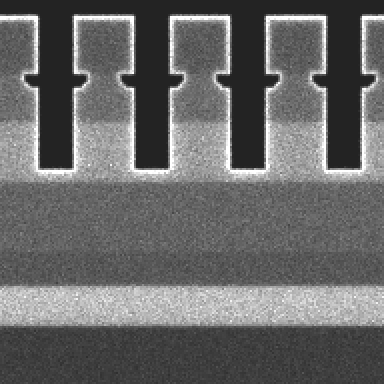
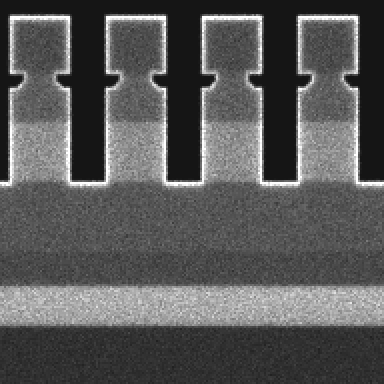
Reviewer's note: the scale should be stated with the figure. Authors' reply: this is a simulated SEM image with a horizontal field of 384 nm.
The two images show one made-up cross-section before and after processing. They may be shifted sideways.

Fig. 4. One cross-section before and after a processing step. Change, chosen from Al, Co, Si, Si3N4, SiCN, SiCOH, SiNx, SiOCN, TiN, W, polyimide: Co removed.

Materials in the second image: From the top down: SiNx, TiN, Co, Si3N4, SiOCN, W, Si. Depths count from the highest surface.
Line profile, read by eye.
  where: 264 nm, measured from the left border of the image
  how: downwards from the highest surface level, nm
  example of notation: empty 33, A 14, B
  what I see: empty 166, Si3N4 70, SiOCN 34, W 40, Si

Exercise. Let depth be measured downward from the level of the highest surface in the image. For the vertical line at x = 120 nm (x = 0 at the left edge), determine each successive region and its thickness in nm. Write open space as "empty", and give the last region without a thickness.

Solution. SiNx 58, TiN 48, Co 60, Si3N4 70, SiOCN 34, W 40, Si